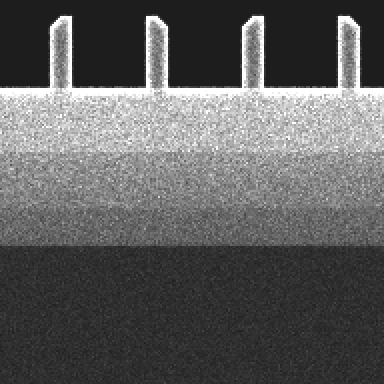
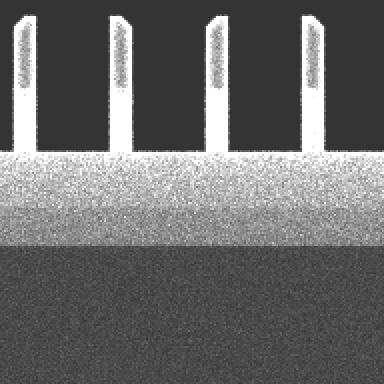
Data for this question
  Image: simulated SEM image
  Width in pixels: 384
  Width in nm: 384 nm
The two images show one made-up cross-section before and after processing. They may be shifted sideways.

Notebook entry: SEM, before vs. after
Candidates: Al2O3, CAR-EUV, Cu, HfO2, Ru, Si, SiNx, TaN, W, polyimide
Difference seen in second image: HfO2 removed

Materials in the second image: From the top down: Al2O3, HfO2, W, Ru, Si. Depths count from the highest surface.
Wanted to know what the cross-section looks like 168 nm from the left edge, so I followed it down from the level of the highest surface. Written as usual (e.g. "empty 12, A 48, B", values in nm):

empty 136, W 56, Ru 38, Si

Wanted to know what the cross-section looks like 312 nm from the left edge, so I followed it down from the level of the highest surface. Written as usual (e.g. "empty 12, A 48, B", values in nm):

Al2O3 72, HfO2 64, W 56, Ru 38, Si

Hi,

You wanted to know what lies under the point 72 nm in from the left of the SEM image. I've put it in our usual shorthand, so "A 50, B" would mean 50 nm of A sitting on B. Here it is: empty 136, W 56, Ru 38, Si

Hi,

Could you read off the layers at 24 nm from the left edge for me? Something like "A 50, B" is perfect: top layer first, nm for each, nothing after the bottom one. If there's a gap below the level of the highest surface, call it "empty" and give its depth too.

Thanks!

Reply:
Al2O3 72, HfO2 64, W 56, Ru 38, Si